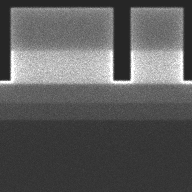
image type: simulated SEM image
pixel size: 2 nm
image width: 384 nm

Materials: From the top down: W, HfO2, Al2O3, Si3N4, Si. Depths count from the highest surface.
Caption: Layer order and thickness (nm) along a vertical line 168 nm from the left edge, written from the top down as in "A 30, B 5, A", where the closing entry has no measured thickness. W 86, HfO2 66, Al2O3 38, Si3N4 34, Si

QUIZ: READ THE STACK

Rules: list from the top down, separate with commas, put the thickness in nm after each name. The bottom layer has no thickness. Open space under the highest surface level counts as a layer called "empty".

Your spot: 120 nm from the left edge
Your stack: W 86, HfO2 66, Al2O3 38, Si3N4 34, Si